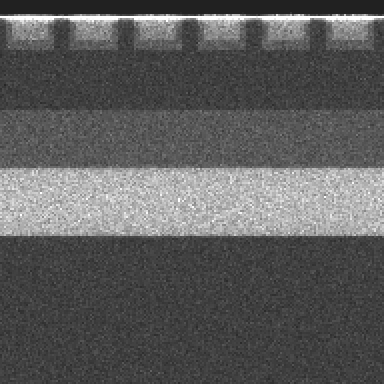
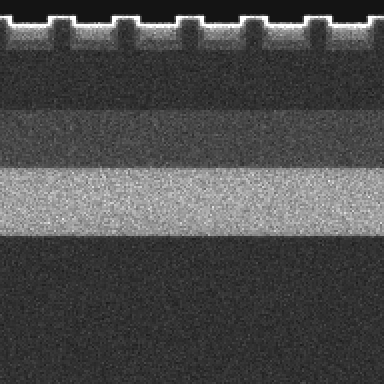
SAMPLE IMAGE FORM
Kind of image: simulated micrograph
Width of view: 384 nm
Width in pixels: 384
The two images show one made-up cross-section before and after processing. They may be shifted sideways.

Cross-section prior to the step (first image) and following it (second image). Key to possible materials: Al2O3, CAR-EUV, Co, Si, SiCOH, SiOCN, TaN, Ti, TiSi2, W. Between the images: Co was removed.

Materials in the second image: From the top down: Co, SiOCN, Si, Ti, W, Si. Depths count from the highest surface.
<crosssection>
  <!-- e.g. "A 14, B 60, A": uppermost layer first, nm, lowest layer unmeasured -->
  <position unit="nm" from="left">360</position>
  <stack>empty 8, Co 16, SiOCN 10, Si 60, Ti 58, W 68, Si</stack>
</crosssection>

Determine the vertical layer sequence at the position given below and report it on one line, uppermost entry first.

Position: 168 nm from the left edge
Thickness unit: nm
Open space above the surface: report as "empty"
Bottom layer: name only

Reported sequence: empty 8, Co 16, SiOCN 10, Si 60, Ti 58, W 68, Si